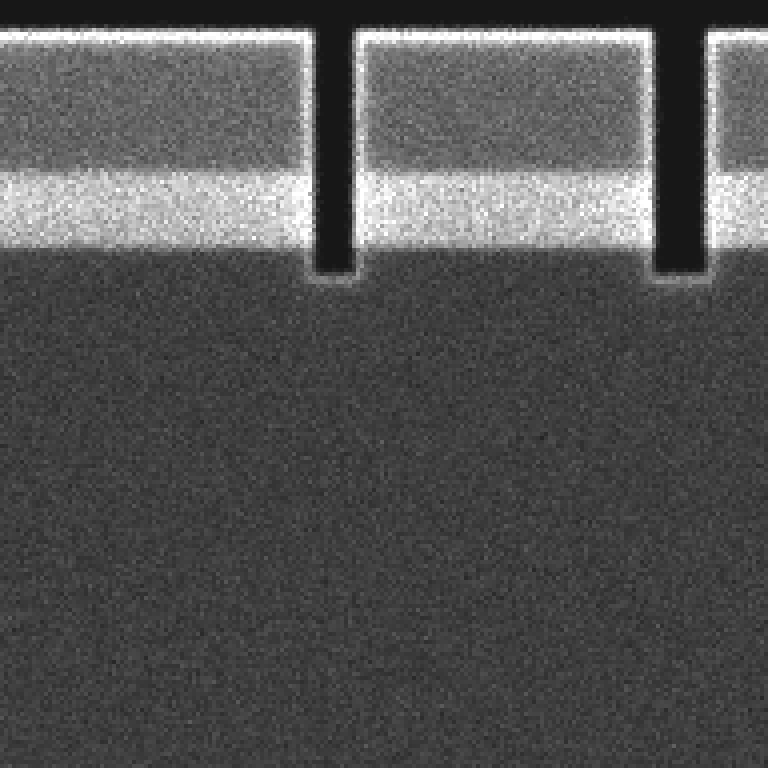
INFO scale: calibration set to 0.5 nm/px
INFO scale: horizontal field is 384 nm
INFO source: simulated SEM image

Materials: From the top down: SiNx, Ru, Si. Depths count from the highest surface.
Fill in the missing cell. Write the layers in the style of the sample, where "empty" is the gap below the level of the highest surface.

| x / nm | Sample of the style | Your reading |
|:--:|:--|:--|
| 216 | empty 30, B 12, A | SiNx 70, Ru 38, Si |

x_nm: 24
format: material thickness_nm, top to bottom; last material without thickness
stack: SiNx 70, Ru 38, Si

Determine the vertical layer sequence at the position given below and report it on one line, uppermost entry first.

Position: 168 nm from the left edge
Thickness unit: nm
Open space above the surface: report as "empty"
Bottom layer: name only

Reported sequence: empty 122, Si